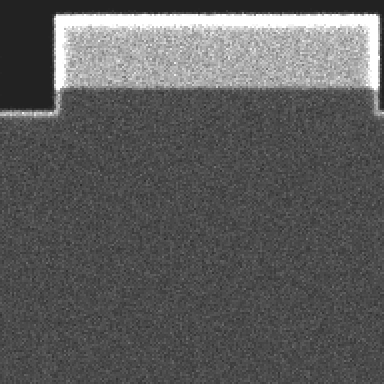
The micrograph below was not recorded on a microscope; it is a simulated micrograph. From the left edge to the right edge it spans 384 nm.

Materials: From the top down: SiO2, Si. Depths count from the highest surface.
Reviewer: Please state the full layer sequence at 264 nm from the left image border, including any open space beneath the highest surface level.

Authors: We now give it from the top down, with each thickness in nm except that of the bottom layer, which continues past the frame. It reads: SiO2 72, Si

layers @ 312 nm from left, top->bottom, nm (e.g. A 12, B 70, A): SiO2 72, Si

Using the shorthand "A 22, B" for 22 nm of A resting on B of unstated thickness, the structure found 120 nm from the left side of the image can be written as SiO2 72, Si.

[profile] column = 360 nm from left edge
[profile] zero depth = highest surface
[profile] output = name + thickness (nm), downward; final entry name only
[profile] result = SiO2 72, Si